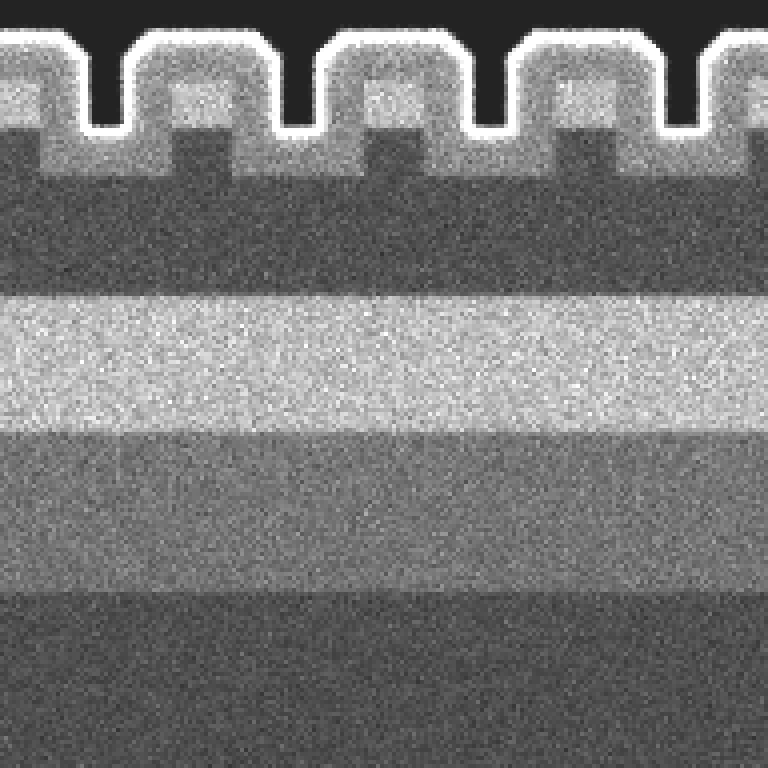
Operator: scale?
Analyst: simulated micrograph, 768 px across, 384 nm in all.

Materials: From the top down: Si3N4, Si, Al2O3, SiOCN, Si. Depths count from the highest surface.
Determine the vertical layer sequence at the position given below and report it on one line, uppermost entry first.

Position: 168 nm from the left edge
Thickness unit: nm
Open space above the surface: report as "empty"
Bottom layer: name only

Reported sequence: empty 2, Si3N4 70, Si 60, Al2O3 68, SiOCN 80, Si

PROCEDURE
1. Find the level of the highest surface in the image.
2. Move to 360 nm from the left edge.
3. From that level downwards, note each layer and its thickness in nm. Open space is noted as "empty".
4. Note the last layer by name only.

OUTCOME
empty 2, Si3N4 70, Si 60, Al2O3 68, SiOCN 80, Si